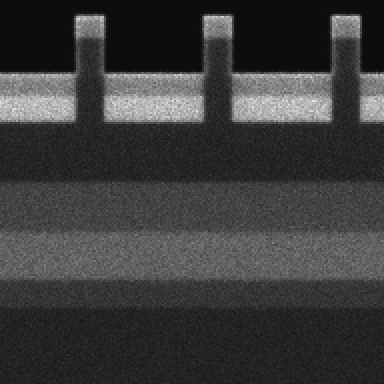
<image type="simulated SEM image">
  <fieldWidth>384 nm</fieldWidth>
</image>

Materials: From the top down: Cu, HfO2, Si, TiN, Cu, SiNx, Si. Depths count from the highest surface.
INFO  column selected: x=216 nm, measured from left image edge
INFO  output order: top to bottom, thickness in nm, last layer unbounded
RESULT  Cu 22, Si 144, TiN 50, Cu 48, SiNx 28, Si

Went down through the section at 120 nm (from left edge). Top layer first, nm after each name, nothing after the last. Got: empty 58, Cu 22, HfO2 26, Si 60, TiN 50, Cu 48, SiNx 28, Si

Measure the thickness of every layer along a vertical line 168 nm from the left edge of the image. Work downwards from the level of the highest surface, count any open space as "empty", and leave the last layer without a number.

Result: empty 58, Cu 22, HfO2 26, Si 60, TiN 50, Cu 48, SiNx 28, Si